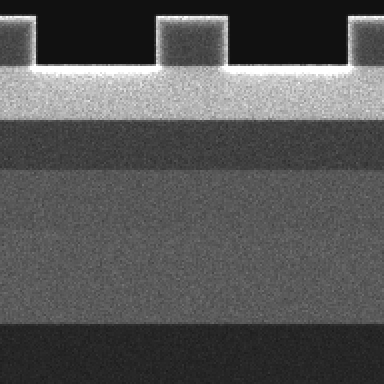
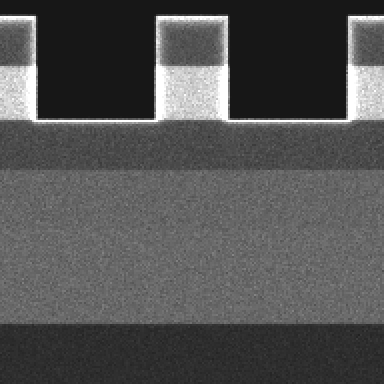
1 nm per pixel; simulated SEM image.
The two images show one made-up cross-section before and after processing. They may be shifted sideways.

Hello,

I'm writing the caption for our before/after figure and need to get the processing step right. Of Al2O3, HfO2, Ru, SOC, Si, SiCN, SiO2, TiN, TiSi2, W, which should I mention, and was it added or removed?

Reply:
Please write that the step removed HfO2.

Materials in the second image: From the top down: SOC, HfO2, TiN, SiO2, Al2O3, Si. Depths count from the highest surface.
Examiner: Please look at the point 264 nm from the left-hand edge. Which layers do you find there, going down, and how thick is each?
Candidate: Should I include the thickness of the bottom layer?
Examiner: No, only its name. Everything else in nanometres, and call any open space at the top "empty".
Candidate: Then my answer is empty 104, TiN 50, SiO2 60, Al2O3 94, Si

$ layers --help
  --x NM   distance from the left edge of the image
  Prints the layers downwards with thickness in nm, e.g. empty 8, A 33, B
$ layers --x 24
SOC 50, HfO2 54, TiN 50, SiO2 60, Al2O3 94, Si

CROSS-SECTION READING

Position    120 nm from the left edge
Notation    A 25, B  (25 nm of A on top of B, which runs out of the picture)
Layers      empty 104, TiN 50, SiO2 60, Al2O3 94, Si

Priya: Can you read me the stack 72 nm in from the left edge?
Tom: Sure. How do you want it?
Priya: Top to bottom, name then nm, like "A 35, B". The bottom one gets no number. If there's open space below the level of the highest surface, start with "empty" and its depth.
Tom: empty 104, TiN 50, SiO2 60, Al2O3 94, Si